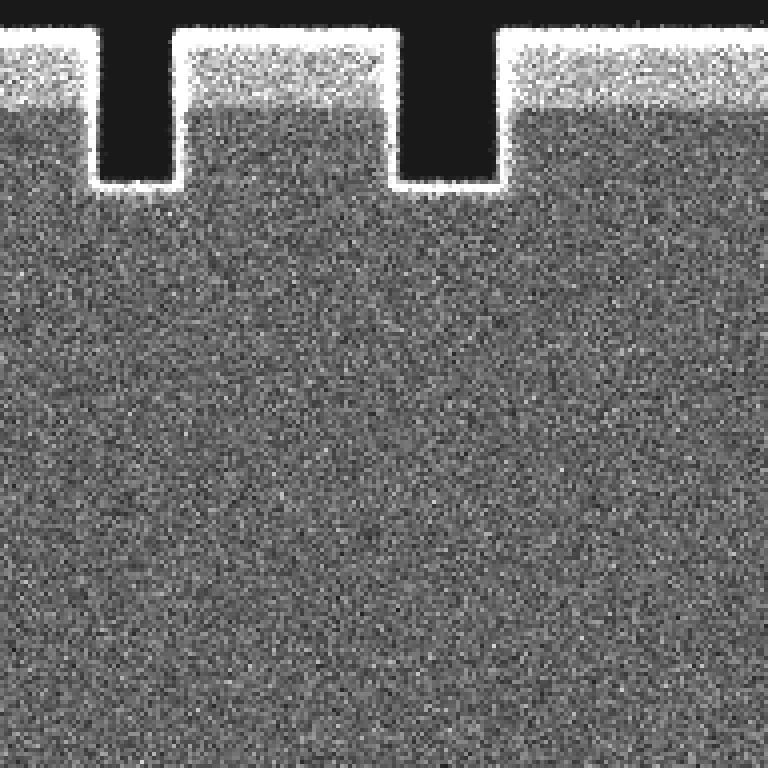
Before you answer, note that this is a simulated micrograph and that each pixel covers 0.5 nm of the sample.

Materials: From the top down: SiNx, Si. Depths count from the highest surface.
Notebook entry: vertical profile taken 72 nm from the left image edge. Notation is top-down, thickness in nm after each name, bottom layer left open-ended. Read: empty 76, Si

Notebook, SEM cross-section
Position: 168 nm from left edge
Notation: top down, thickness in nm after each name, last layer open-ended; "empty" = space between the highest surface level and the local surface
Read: SiNx 38, Si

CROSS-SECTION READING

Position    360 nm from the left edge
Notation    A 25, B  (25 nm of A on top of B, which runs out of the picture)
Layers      SiNx 38, Si